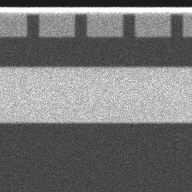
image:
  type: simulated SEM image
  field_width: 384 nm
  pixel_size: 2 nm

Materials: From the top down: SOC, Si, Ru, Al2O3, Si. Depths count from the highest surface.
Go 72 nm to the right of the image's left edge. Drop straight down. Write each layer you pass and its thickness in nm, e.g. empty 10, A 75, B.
SOC 12, Si 106, Ru 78, Al2O3 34, Si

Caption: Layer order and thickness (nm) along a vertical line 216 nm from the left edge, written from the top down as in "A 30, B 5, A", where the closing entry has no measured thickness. SOC 58, Si 60, Ru 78, Al2O3 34, Si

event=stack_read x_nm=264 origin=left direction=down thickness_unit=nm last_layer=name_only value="SOC 12, Si 106, Ru 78, Al2O3 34, Si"